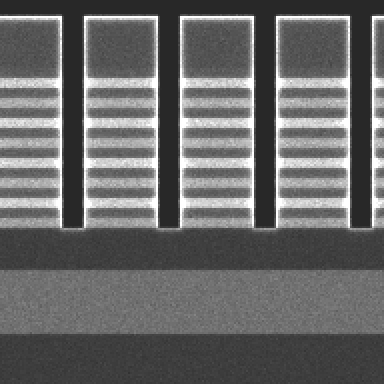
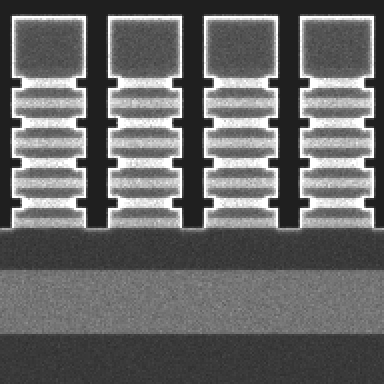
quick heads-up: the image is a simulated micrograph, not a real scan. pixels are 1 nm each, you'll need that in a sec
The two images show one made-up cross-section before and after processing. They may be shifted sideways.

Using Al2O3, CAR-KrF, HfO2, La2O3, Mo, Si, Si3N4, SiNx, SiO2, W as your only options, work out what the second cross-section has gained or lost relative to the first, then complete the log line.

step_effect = removed HfO2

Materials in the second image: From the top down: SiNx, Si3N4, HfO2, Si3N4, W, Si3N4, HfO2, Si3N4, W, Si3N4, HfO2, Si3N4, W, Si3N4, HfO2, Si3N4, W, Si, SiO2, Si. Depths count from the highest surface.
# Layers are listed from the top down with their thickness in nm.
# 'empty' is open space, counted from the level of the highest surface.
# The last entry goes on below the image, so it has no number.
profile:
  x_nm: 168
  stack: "SiNx 52, Si3N4 10, HfO2 10, Si3N4 10, W 10, Si3N4 10, HfO2 10, Si3N4 10, W 10, Si3N4 10, HfO2 10, Si3N4 10, W 10, Si3N4 10, HfO2 10, Si3N4 10, W 10, Si 42, SiO2 64, Si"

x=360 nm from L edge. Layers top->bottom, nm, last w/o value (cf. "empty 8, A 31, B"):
SiNx 52, Si3N4 10, HfO2 10, Si3N4 10, W 10, Si3N4 10, HfO2 10, Si3N4 10, W 10, Si3N4 10, HfO2 10, Si3N4 10, W 10, Si3N4 10, HfO2 10, Si3N4 10, W 10, Si 42, SiO2 64, Si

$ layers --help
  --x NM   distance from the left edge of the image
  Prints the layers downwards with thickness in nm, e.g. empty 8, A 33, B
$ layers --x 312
SiNx 52, Si3N4 10, HfO2 10, Si3N4 10, W 10, Si3N4 10, HfO2 10, Si3N4 10, W 10, Si3N4 10, HfO2 10, Si3N4 10, W 10, Si3N4 10, HfO2 10, Si3N4 10, W 10, Si 42, SiO2 64, Si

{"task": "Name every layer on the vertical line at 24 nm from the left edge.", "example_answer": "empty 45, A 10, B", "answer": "SiNx 52, Si3N4 10, HfO2 10, Si3N4 10, W 10, Si3N4 10, HfO2 10, Si3N4 10, W 10, Si3N4 10, HfO2 10, Si3N4 10, W 10, Si3N4 10, HfO2 10, Si3N4 10, W 10, Si 42, SiO2 64, Si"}